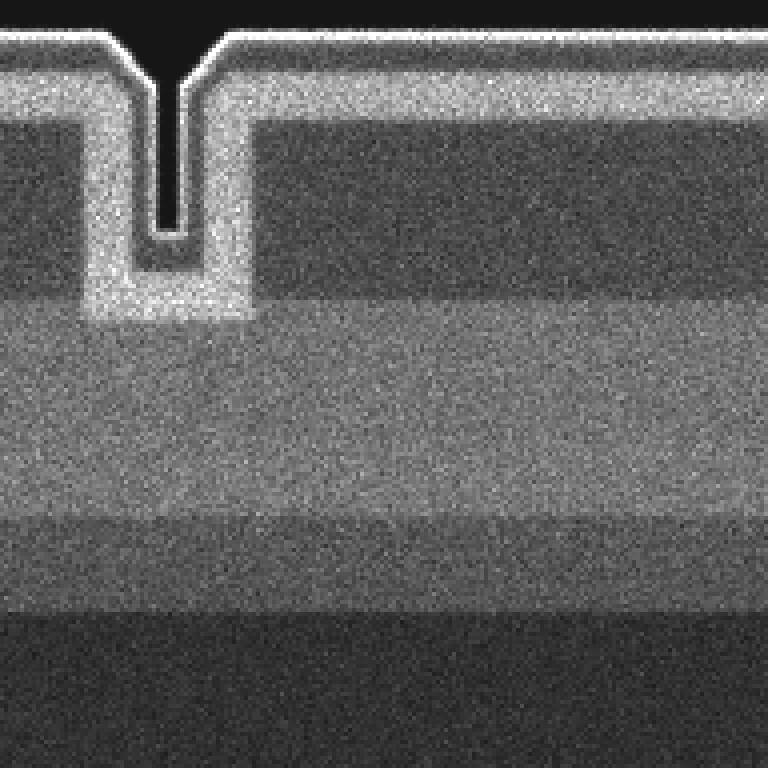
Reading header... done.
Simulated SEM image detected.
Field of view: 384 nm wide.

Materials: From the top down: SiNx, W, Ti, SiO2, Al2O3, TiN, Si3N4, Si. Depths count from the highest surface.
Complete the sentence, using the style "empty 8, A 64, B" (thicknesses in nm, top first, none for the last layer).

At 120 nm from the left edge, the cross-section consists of SiNx 20, W 124, SiO2 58, Al2O3 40, TiN 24, Si3N4 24, Si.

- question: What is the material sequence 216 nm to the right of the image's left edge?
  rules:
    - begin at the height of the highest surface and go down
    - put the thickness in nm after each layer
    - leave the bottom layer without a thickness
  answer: SiNx 20, W 24, Ti 90, SiO2 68, Al2O3 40, TiN 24, Si3N4 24, Si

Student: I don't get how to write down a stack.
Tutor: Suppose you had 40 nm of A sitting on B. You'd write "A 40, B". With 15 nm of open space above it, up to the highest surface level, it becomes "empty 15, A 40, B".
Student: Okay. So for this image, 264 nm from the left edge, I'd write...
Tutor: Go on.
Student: SiNx 20, W 24, Ti 90, SiO2 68, Al2O3 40, TiN 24, Si3N4 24, Si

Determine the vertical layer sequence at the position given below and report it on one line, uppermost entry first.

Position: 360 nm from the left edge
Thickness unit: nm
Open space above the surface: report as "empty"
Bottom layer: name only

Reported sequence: SiNx 20, W 24, Ti 90, SiO2 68, Al2O3 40, TiN 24, Si3N4 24, Si